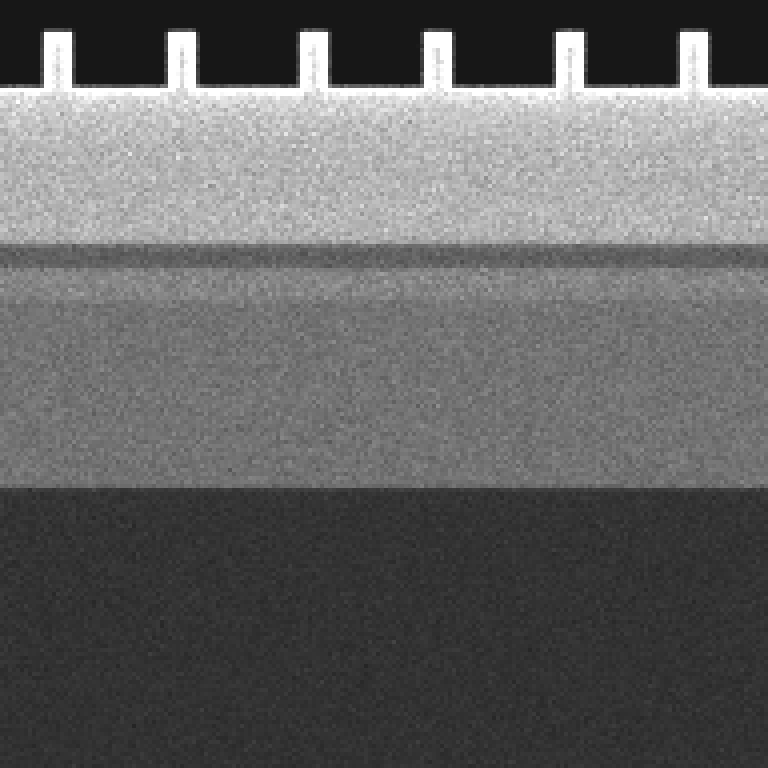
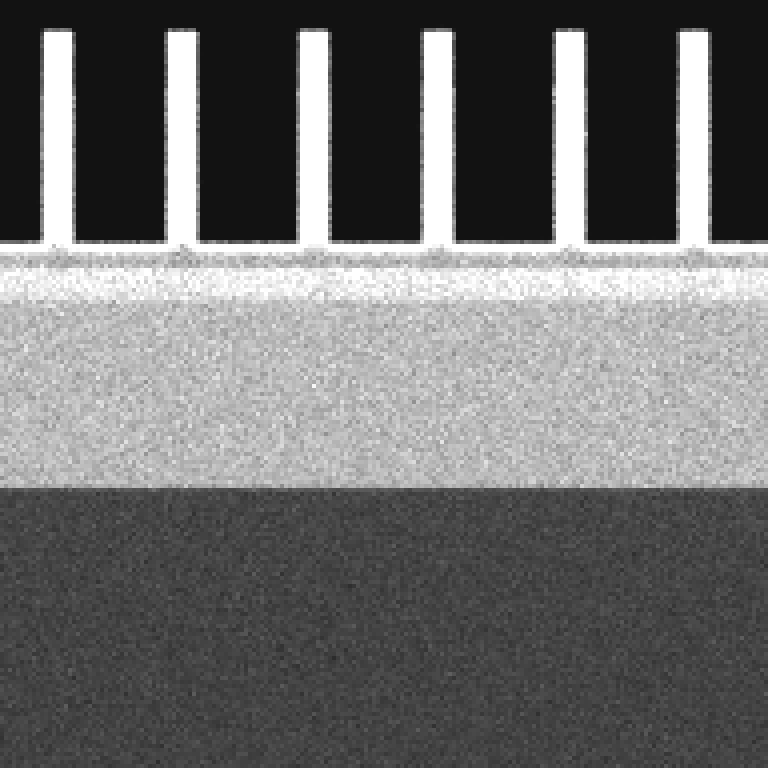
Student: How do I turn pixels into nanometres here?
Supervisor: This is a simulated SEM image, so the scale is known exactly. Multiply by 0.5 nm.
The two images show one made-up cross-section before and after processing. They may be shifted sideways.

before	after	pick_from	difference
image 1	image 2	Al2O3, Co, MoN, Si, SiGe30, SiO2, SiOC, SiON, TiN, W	W removed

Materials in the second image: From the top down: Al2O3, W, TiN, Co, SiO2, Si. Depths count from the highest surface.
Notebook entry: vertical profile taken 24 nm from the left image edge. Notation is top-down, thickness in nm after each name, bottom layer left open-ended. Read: Al2O3 28, W 78, TiN 12, Co 16, SiO2 94, Si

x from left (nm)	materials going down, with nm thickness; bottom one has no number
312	empty 106, TiN 12, Co 16, SiO2 94, Si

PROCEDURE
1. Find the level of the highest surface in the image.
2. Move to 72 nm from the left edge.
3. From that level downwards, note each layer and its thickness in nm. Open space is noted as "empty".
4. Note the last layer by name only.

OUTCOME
empty 106, TiN 12, Co 16, SiO2 94, Si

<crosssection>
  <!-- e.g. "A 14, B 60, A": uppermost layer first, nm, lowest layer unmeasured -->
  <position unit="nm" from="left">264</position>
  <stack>empty 106, TiN 12, Co 16, SiO2 94, Si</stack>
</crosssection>